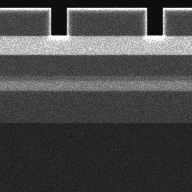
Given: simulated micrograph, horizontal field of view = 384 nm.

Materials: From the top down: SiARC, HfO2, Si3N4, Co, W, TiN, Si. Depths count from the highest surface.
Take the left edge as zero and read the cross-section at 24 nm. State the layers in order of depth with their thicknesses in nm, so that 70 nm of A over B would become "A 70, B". SiARC 56, HfO2 38, Si3N4 42, Co 10, W 20, TiN 64, Si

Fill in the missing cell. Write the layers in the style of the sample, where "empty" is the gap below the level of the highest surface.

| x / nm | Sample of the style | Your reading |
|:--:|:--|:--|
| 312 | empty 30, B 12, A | empty 56, HfO2 38, Si3N4 42, Co 10, W 20, TiN 64, Si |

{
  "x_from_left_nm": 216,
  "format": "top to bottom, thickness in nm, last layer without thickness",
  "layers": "SiARC 56, HfO2 38, Si3N4 42, Co 10, W 20, TiN 64, Si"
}